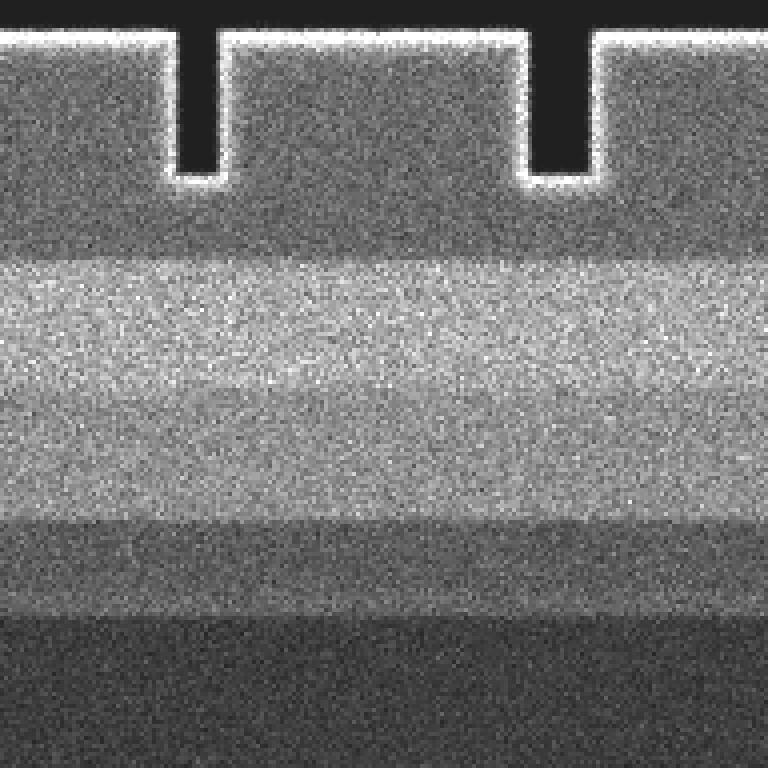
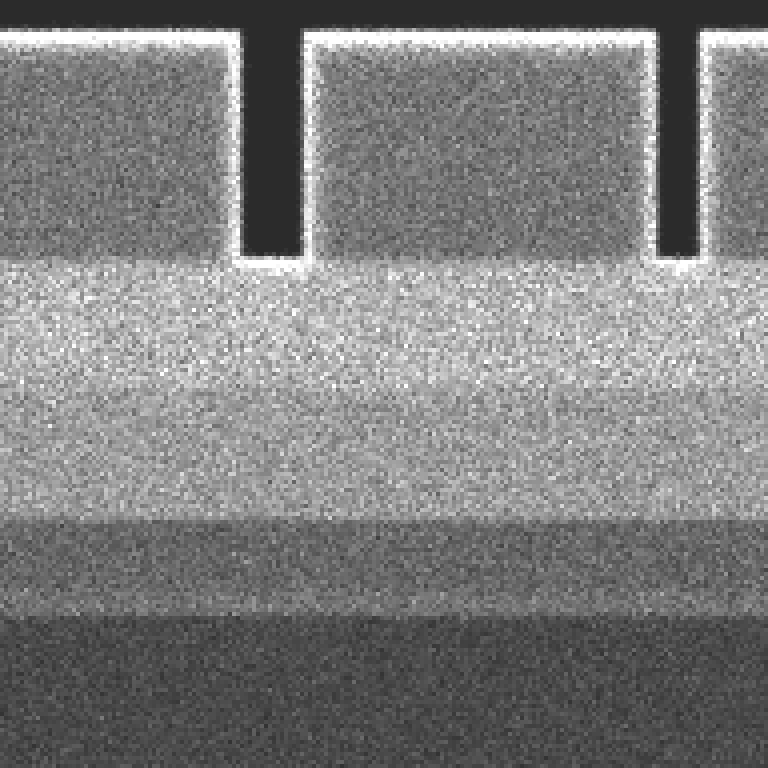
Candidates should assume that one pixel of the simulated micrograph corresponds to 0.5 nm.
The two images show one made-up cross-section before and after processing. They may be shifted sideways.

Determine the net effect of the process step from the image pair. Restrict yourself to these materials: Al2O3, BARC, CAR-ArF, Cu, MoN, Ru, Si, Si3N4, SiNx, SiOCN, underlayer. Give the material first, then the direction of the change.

underlayer: removed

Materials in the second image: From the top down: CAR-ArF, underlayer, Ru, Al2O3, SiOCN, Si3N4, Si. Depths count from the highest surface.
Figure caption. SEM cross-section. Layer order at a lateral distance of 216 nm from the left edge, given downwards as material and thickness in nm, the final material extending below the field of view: CAR-ArF 72, underlayer 42, Ru 64, Al2O3 66, SiOCN 36, Si3N4 12, Si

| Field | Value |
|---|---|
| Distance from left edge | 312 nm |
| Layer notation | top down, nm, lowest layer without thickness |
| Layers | CAR-ArF 72, underlayer 42, Ru 64, Al2O3 66, SiOCN 36, Si3N4 12, Si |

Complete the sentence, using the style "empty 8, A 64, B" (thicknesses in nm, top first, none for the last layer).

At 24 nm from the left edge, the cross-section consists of CAR-ArF 72, underlayer 42, Ru 64, Al2O3 66, SiOCN 36, Si3N4 12, Si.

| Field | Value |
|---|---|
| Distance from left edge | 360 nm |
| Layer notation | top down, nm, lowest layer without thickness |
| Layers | CAR-ArF 72, underlayer 42, Ru 64, Al2O3 66, SiOCN 36, Si3N4 12, Si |